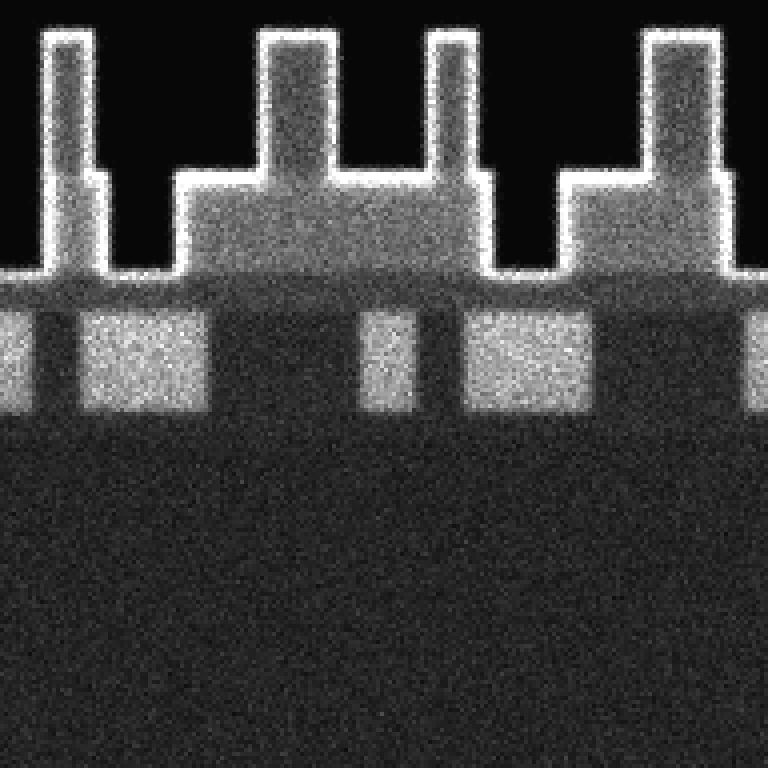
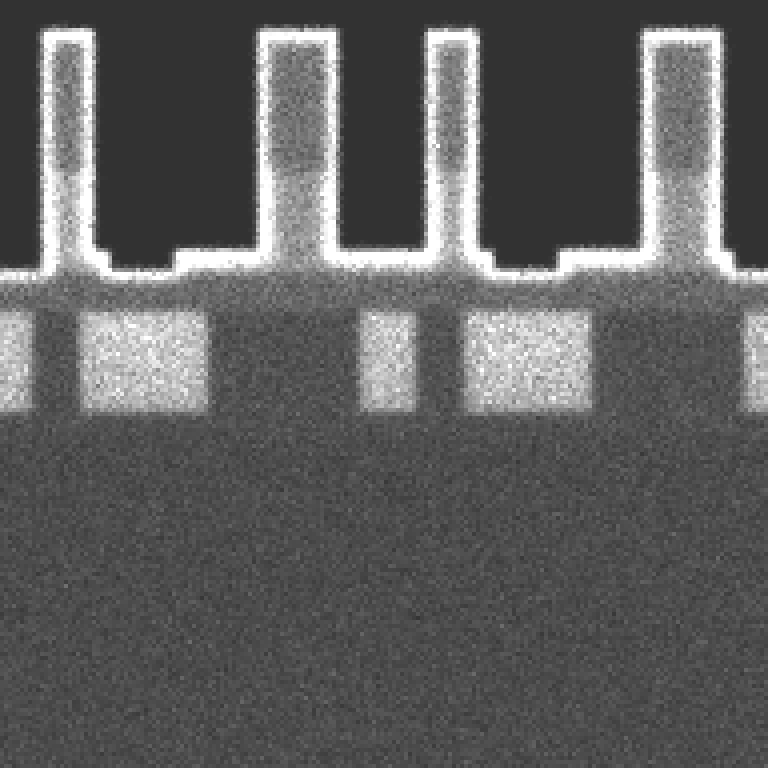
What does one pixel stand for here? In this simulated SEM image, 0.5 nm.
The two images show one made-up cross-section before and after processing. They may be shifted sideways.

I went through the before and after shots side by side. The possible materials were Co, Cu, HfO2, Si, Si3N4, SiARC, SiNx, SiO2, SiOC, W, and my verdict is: removed, SiO2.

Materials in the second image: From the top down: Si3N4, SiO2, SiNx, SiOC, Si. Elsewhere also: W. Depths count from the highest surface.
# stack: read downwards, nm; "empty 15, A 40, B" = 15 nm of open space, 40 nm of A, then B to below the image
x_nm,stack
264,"empty 120, SiNx 20, W 50, SiOC 12, Si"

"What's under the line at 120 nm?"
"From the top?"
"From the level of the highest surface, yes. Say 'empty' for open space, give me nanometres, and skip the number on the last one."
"empty 110, SiO2 10, SiNx 20, SiOC 62, Si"